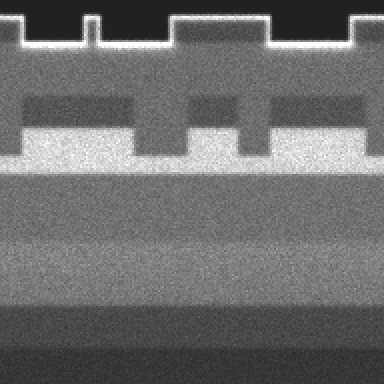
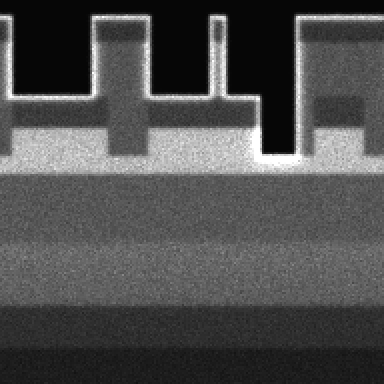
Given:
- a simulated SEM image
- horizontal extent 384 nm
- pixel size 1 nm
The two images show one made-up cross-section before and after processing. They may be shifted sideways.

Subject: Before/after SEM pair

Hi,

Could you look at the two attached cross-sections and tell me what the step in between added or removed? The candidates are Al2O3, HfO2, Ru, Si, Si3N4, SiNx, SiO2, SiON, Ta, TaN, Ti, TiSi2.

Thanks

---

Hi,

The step removed SiO2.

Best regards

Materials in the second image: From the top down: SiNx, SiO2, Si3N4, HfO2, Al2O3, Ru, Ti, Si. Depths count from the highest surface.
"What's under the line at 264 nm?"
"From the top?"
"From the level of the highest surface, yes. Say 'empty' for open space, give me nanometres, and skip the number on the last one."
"empty 140, HfO2 18, Al2O3 68, Ru 64, Ti 42, Si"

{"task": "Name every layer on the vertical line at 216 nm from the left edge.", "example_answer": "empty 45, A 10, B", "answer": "SiNx 26, SiO2 54, Si3N4 32, HfO2 46, Al2O3 68, Ru 64, Ti 42, Si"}